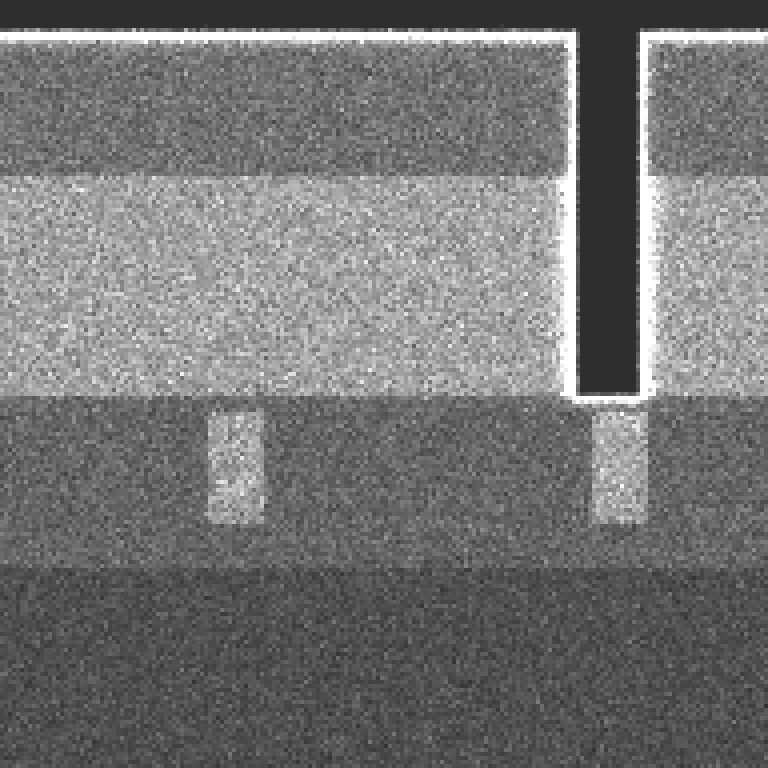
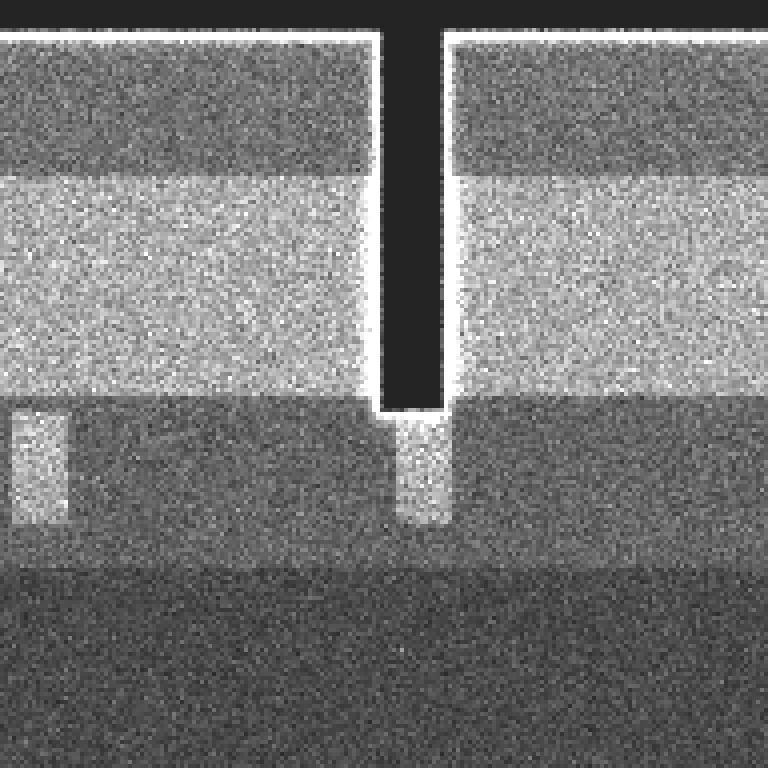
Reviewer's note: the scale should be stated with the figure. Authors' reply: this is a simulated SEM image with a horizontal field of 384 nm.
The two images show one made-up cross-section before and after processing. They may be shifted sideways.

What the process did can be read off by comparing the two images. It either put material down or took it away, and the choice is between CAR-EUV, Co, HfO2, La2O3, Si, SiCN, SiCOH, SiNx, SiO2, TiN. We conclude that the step removed SiCN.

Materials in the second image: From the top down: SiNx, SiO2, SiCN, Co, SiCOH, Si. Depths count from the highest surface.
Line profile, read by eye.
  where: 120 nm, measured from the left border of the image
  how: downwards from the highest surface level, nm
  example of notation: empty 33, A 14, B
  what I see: SiNx 72, SiO2 110, SiCN 8, SiCOH 78, Si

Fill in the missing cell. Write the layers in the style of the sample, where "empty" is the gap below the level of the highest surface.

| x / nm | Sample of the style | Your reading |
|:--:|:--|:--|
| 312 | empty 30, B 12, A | SiNx 72, SiO2 110, SiCN 8, SiCOH 78, Si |